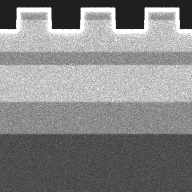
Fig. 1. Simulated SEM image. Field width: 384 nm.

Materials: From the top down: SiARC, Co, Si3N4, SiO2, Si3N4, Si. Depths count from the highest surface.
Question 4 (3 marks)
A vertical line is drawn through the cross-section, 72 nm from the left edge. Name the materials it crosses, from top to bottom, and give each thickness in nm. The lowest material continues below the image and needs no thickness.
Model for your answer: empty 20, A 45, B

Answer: SiARC 24, Co 64, Si3N4 26, SiO2 74, Si3N4 64, Si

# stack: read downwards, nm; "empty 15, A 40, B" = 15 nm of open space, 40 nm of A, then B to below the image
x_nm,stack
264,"empty 44, Co 44, Si3N4 26, SiO2 74, Si3N4 64, Si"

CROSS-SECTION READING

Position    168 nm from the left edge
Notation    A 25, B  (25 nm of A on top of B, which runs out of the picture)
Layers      SiARC 24, Co 64, Si3N4 26, SiO2 74, Si3N4 64, Si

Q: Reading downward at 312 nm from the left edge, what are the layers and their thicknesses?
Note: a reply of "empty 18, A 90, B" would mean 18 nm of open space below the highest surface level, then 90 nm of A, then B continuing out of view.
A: SiARC 24, Co 64, Si3N4 26, SiO2 74, Si3N4 64, Si